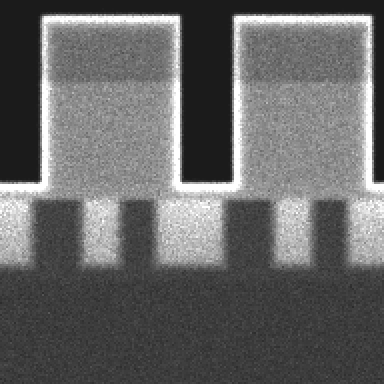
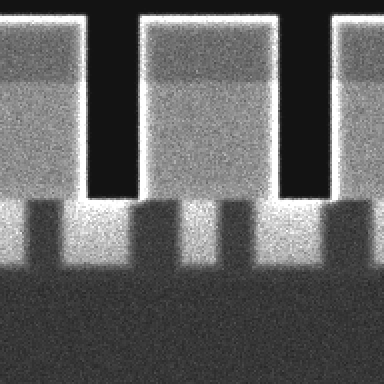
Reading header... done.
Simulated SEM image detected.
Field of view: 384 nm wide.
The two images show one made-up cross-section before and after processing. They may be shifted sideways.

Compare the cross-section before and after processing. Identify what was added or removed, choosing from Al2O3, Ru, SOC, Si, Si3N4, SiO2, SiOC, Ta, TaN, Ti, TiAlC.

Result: Al2O3 removed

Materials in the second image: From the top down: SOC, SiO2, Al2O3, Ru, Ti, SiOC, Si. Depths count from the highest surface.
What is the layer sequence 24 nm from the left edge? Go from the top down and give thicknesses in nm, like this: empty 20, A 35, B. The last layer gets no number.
SOC 66, SiO2 102, Al2O3 16, Ti 70, SiOC 12, Si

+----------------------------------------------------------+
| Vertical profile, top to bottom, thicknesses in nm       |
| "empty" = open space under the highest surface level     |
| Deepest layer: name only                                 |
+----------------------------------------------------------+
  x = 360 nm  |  SOC 66, SiO2 102, Al2O3 16, SiOC 82, Si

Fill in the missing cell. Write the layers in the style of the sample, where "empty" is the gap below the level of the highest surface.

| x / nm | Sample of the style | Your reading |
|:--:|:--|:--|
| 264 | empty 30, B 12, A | SOC 66, SiO2 102, Al2O3 16, Ru 64, Ti 6, SiOC 12, Si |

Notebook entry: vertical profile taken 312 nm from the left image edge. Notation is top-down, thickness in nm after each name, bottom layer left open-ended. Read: empty 184, Ru 64, Ti 6, SiOC 12, Si